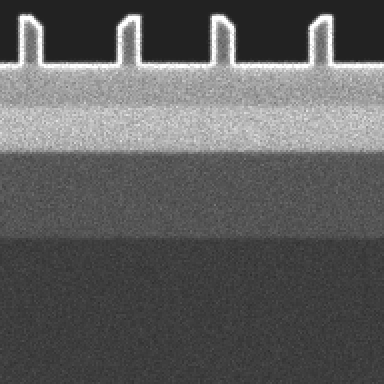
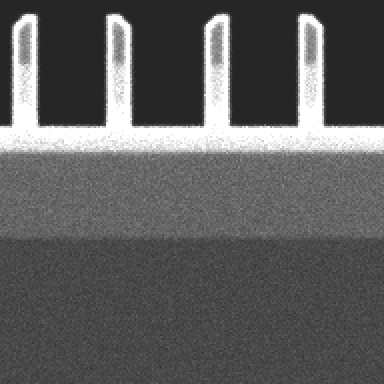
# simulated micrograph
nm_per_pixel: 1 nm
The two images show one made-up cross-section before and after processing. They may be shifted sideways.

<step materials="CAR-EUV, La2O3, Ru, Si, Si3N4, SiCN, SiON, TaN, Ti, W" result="removed Ru and W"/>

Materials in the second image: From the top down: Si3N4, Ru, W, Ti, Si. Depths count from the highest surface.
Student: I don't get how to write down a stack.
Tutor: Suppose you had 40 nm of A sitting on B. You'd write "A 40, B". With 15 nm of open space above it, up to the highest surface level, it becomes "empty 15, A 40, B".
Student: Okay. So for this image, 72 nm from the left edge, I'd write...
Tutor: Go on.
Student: empty 112, W 24, Ti 86, Si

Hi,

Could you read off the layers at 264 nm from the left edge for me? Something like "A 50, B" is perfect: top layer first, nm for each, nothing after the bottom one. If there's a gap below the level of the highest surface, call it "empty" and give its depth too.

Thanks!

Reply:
empty 112, W 24, Ti 86, Si